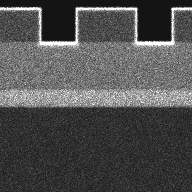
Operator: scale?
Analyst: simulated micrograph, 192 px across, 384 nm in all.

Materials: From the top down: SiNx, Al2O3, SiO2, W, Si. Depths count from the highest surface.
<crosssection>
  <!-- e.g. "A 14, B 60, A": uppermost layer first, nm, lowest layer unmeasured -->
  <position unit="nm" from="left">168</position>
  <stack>SiNx 68, Al2O3 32, SiO2 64, W 34, Si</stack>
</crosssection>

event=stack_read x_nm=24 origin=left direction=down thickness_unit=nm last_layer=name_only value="SiNx 68, Al2O3 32, SiO2 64, W 34, Si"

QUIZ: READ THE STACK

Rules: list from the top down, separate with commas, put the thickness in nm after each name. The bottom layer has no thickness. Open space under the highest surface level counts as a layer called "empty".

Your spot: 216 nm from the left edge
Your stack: SiNx 68, Al2O3 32, SiO2 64, W 34, Si